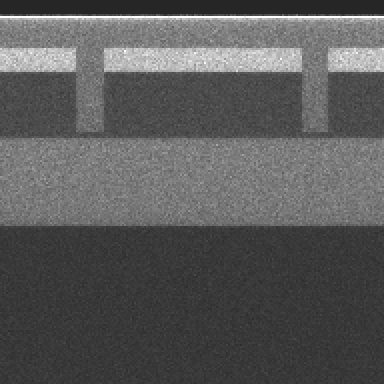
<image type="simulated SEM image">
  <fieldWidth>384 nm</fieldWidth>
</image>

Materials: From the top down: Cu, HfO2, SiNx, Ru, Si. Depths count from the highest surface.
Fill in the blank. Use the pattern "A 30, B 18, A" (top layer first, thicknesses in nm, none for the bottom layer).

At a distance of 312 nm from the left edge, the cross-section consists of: Cu 116, SiNx 6, Ru 88, Si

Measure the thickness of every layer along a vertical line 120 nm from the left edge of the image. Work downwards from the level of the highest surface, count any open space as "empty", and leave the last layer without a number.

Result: Cu 32, HfO2 24, SiNx 66, Ru 88, Si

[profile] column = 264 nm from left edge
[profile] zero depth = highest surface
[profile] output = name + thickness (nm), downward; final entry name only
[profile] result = Cu 32, HfO2 24, SiNx 66, Ru 88, Si